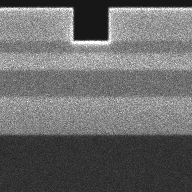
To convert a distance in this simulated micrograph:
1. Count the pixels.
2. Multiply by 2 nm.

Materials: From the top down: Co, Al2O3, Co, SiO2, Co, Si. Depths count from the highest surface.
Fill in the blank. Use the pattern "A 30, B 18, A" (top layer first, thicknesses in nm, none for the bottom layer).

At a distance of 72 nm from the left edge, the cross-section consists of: Co 66, Al2O3 24, Co 34, SiO2 54, Co 76, Si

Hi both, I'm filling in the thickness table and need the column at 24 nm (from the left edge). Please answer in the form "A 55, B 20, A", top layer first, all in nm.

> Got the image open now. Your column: Co 66, Al2O3 24, Co 34, SiO2 54, Co 76, Si